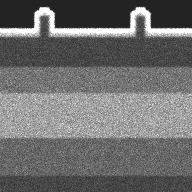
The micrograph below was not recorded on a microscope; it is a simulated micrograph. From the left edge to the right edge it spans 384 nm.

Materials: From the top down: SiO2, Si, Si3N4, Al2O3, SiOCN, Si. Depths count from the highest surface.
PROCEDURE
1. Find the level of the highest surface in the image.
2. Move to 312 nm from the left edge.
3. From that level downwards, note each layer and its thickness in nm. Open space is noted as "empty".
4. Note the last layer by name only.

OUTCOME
empty 42, SiO2 16, Si 60, Si3N4 52, Al2O3 90, SiOCN 76, Si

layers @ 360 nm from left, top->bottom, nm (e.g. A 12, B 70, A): empty 42, SiO2 16, Si 60, Si3N4 52, Al2O3 90, SiOCN 76, Si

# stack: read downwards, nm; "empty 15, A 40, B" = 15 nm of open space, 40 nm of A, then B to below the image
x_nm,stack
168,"empty 42, SiO2 16, Si 60, Si3N4 52, Al2O3 90, SiOCN 76, Si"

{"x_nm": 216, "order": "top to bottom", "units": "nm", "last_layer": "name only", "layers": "empty 42, SiO2 16, Si 60, Si3N4 52, Al2O3 90, SiOCN 76, Si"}